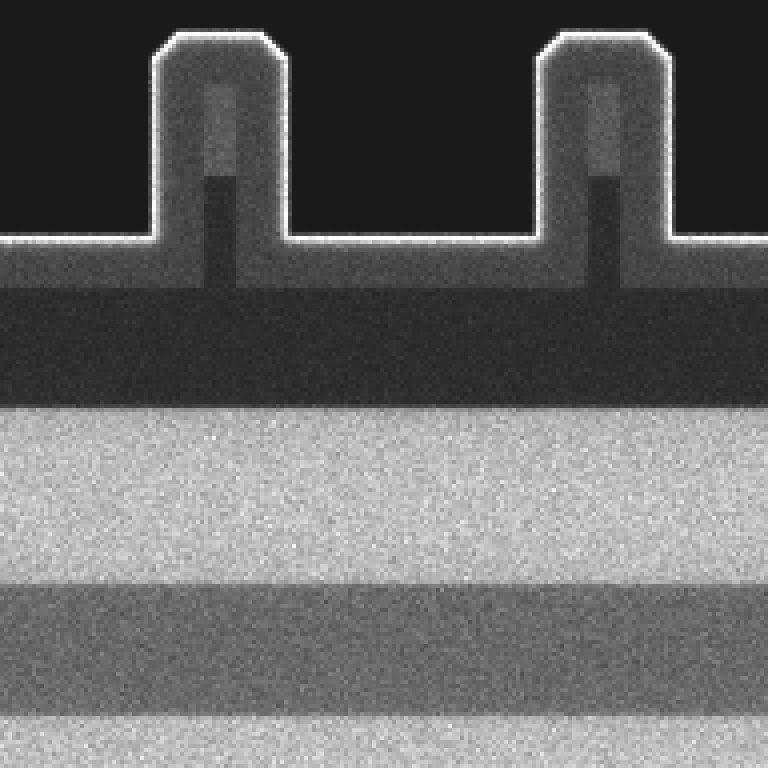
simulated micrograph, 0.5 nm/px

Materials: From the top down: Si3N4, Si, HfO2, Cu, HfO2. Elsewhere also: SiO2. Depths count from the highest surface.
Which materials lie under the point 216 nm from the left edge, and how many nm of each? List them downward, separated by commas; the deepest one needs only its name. empty 102, Si3N4 26, Si 60, HfO2 88, Cu 66, HfO2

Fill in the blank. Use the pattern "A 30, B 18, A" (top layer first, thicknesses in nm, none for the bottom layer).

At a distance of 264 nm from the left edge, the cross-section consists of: empty 102, Si3N4 26, Si 60, HfO2 88, Cu 66, HfO2